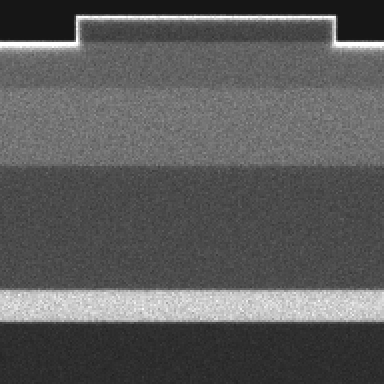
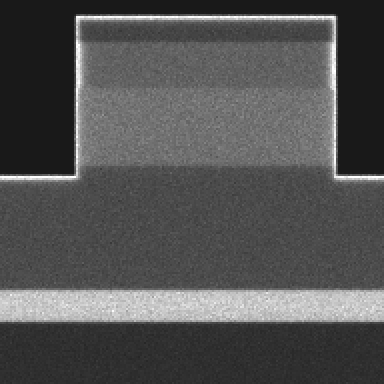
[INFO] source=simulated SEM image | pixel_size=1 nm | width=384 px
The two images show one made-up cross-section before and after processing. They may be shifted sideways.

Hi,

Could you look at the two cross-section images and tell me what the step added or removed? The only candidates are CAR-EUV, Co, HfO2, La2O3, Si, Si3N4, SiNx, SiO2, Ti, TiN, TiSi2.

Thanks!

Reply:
removed Co and SiO2 and TiN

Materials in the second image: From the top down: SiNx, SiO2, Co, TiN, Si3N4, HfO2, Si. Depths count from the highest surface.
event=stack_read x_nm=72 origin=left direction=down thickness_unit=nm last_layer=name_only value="empty 160, Si3N4 114, HfO2 32, Si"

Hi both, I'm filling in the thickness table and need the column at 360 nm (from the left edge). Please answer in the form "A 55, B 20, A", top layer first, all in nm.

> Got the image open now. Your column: empty 160, Si3N4 114, HfO2 32, Si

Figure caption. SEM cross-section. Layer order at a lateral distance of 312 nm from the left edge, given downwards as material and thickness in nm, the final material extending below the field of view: SiNx 26, SiO2 46, Co 78, TiN 10, Si3N4 114, HfO2 32, Si